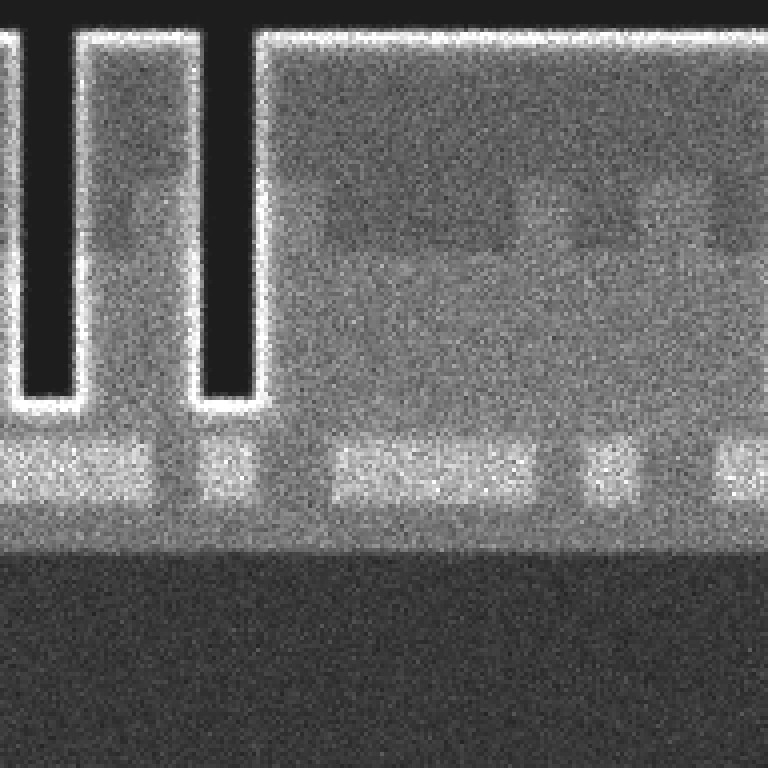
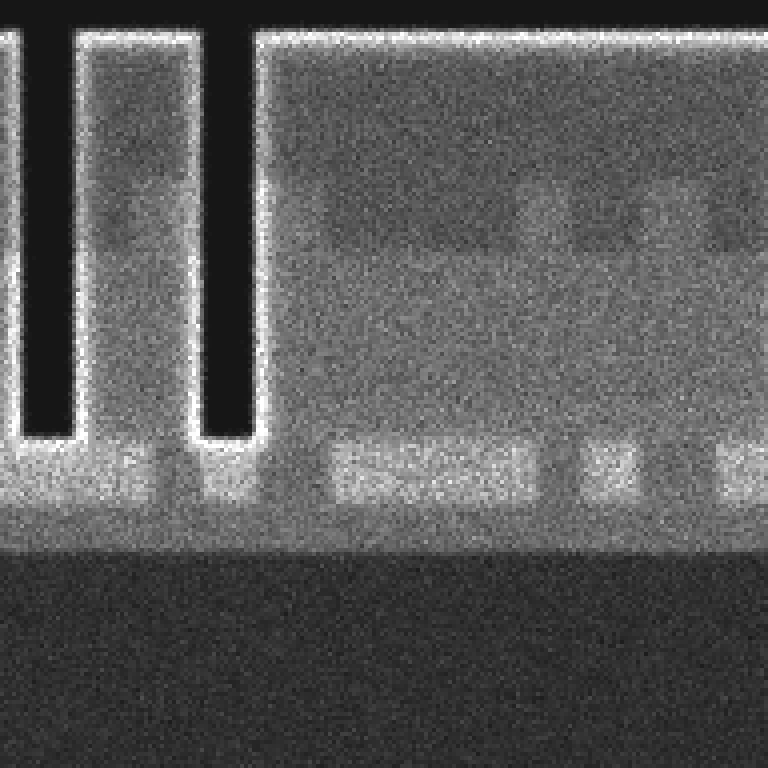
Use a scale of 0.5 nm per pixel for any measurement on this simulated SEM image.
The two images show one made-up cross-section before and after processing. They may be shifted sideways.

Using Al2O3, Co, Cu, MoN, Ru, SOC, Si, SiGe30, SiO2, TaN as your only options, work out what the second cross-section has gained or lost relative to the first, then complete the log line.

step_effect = removed Al2O3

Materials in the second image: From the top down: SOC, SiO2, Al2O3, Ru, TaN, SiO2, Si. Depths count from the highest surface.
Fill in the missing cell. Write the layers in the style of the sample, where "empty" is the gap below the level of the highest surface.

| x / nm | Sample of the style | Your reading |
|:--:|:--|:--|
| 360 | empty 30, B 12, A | SOC 110, SiO2 74, Al2O3 20, TaN 32, SiO2 24, Si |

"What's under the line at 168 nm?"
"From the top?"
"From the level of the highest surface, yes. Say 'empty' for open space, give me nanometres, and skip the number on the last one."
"SOC 110, SiO2 74, Al2O3 20, TaN 32, SiO2 24, Si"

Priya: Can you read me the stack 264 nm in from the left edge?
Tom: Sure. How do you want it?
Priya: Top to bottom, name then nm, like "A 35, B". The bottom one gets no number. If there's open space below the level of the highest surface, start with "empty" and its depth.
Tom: SOC 74, SiO2 110, Al2O3 20, TaN 32, SiO2 24, Si